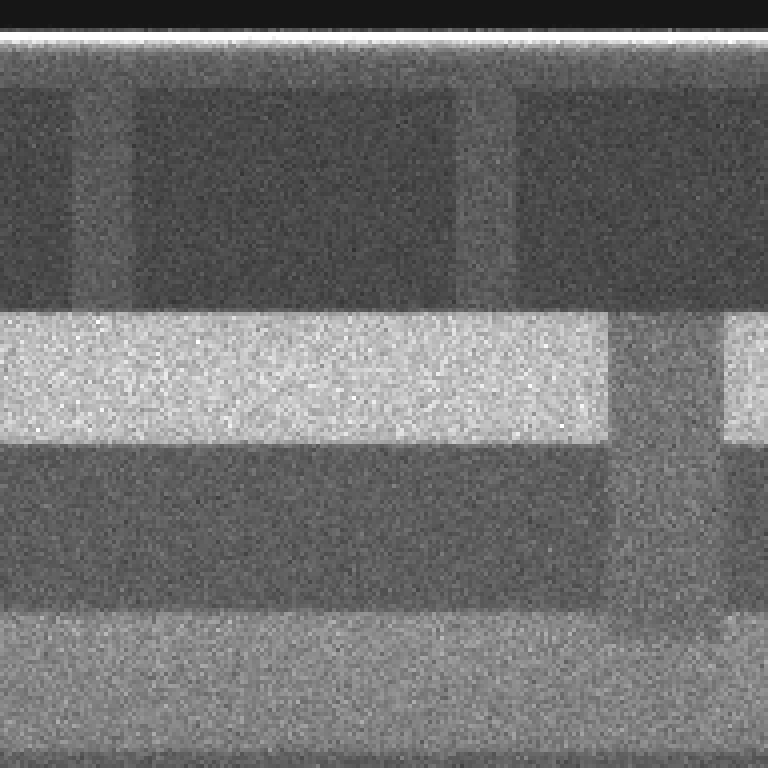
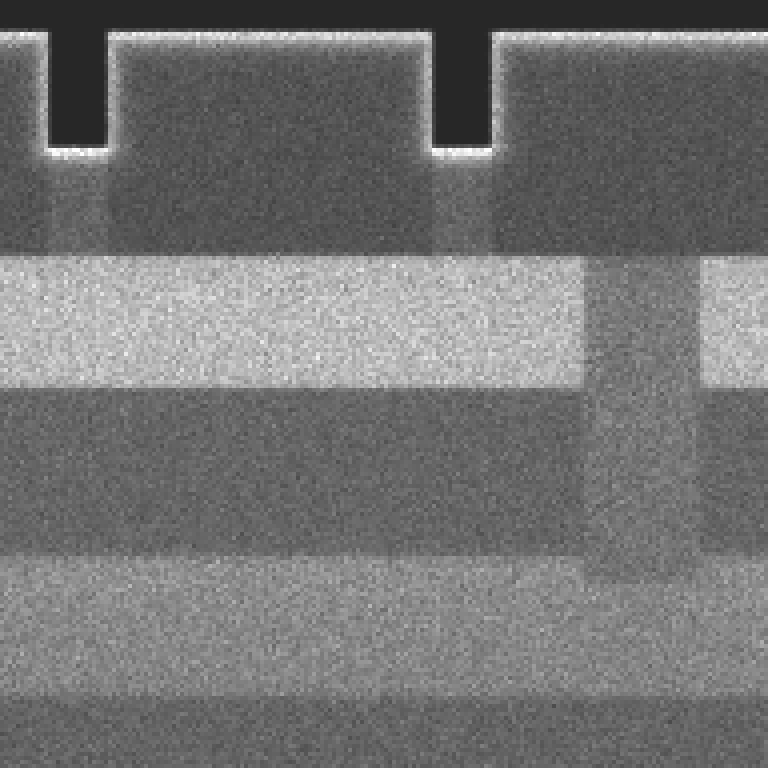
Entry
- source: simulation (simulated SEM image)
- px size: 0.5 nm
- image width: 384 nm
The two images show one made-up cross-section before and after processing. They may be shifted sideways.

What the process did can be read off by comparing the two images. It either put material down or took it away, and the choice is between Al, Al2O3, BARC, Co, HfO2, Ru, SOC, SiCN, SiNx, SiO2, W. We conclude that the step removed SiO2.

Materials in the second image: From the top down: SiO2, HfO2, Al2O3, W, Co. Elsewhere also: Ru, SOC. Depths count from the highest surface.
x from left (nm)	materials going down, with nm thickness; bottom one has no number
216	empty 58, SiO2 54, HfO2 66, Al2O3 84, W 70, Co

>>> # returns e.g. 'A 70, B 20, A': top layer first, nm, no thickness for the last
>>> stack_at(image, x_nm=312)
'SOC 112, Ru 164, W 56, Co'